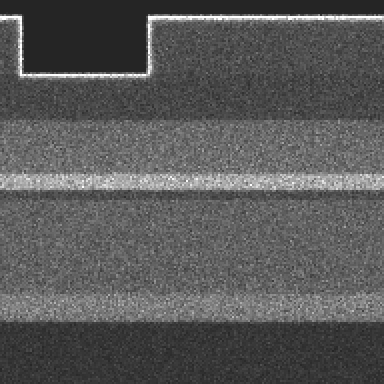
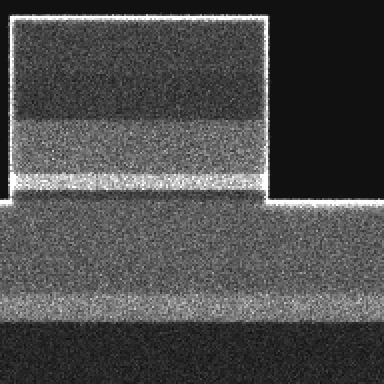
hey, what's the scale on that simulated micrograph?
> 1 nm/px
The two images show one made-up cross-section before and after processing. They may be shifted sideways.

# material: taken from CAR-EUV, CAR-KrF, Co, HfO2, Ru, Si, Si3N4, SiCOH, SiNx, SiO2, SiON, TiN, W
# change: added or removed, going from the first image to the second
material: HfO2 and Ru and SiNx and TiN
change: removed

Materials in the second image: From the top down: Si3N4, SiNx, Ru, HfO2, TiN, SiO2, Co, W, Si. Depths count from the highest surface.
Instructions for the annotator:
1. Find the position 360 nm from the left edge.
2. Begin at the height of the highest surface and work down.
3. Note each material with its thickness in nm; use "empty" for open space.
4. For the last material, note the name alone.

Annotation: empty 184, SiO2 64, Co 30, W 28, Si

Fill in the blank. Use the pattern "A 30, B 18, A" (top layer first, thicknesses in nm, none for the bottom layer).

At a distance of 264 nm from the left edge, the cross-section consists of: Si3N4 58, SiNx 46, Ru 54, HfO2 16, TiN 10, SiO2 64, Co 30, W 28, Si